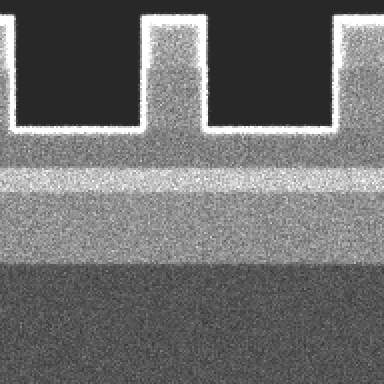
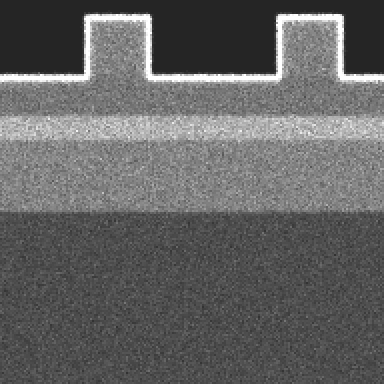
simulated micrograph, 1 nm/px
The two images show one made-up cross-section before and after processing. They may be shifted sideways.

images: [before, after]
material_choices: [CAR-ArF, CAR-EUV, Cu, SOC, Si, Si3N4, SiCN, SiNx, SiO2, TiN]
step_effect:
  removed: SOC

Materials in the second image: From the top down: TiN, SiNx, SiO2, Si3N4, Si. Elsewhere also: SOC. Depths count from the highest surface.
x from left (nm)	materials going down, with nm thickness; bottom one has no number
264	empty 60, SiNx 40, SiO2 24, Si3N4 72, Si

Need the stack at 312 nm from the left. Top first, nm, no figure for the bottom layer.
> TiN 60, SiNx 40, SiO2 24, Si3N4 72, Si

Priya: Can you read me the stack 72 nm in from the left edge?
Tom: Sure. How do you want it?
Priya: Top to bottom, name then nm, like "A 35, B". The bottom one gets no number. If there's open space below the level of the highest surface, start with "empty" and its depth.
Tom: empty 60, SiNx 40, SiO2 24, Si3N4 72, Si